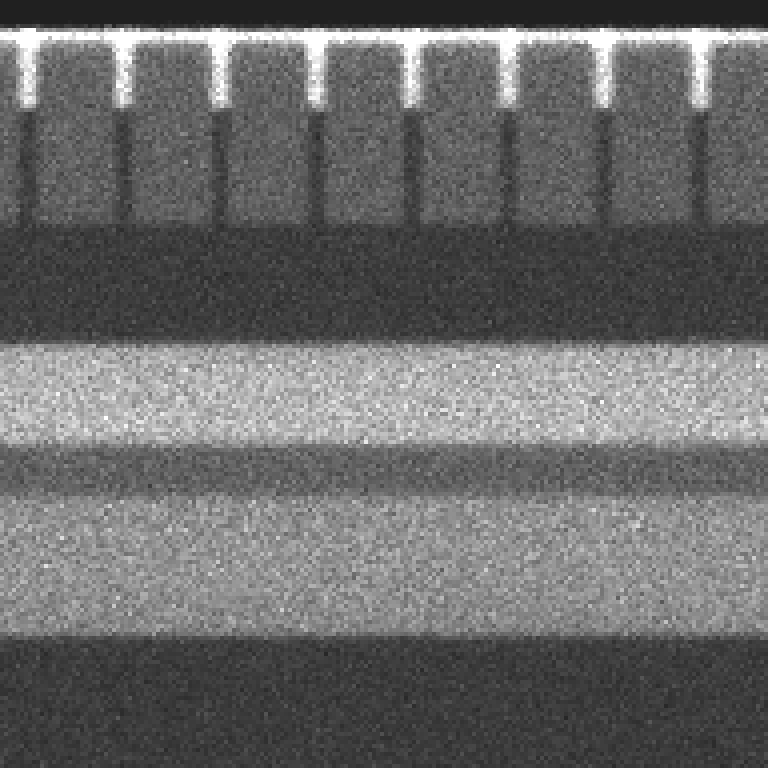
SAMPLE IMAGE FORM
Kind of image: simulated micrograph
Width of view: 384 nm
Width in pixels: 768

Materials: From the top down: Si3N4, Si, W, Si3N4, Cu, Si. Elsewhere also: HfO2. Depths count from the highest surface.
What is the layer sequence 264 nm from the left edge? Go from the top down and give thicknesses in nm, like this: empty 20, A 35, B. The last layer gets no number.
Si3N4 96, Si 60, W 50, Si3N4 26, Cu 70, Si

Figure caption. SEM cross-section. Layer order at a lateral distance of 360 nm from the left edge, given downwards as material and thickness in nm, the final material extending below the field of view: Si3N4 96, Si 60, W 50, Si3N4 26, Cu 70, Si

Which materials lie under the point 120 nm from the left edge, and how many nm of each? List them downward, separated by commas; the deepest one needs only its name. Si3N4 96, Si 60, W 50, Si3N4 26, Cu 70, Si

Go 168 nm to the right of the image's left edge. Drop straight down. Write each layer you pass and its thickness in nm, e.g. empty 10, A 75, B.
Si3N4 96, Si 60, W 50, Si3N4 26, Cu 70, Si